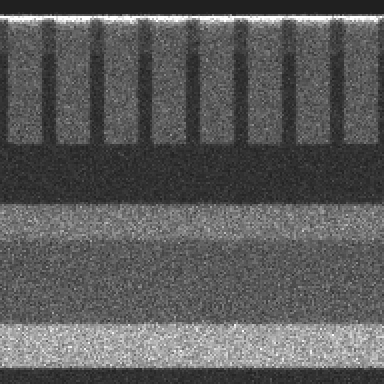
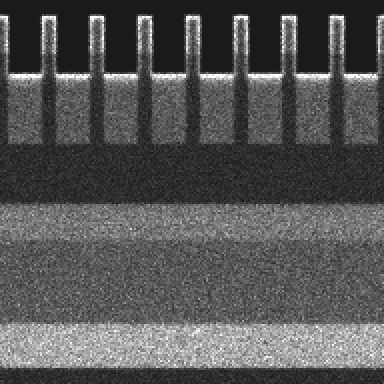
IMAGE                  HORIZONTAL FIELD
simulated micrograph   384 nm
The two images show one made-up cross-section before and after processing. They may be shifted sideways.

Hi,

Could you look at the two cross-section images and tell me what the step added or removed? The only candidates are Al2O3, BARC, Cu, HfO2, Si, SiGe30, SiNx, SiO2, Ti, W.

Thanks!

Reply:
removed SiO2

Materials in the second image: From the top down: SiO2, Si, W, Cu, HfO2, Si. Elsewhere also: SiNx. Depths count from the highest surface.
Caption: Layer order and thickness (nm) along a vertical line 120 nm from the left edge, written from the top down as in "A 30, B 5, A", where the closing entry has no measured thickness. empty 58, SiO2 70, Si 60, W 36, Cu 84, HfO2 44, Si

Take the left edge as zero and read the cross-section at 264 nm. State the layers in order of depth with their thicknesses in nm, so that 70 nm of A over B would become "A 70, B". empty 58, SiO2 70, Si 60, W 36, Cu 84, HfO2 44, Si